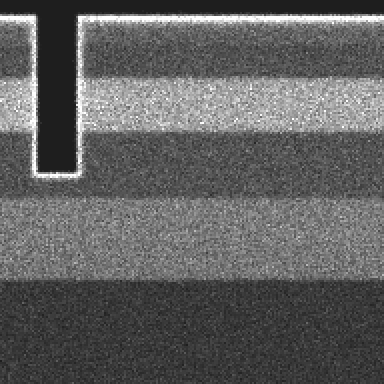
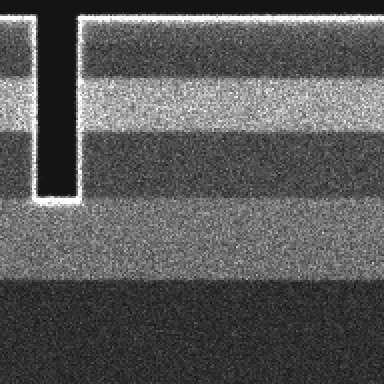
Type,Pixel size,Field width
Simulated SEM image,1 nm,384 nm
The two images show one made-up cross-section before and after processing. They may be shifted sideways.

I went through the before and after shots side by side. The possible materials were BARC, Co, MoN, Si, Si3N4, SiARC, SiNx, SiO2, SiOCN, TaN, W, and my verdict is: removed, SiNx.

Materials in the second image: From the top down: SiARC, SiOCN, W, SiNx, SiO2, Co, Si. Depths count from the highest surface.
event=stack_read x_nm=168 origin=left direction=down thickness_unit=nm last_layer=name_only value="SiARC 28, SiOCN 34, W 54, SiNx 66, SiO2 42, Co 40, Si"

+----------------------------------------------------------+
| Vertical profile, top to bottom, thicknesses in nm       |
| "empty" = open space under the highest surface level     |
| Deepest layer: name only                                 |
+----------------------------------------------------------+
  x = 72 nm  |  empty 182, SiO2 42, Co 40, Si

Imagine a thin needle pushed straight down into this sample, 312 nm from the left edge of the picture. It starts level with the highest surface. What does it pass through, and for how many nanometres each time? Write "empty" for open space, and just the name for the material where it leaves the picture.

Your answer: SiARC 28, SiOCN 34, W 54, SiNx 66, SiO2 42, Co 40, Si